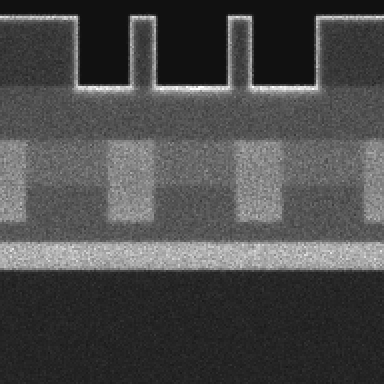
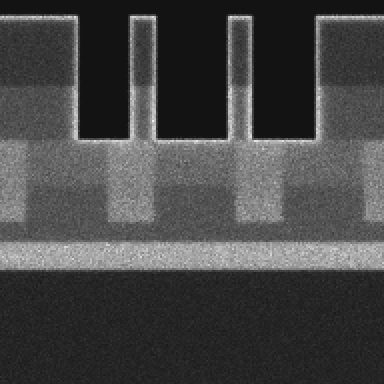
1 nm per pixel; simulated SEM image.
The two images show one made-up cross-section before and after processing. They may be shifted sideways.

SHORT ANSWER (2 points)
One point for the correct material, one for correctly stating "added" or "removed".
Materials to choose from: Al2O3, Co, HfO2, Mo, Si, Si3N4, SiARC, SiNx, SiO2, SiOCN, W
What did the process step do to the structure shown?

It removed SiO2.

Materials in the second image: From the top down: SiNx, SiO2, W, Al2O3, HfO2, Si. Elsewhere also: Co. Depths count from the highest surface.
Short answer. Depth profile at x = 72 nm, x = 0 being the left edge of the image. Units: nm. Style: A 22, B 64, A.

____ SiNx 70, SiO2 54, Co 46, Al2O3 56, HfO2 28, Si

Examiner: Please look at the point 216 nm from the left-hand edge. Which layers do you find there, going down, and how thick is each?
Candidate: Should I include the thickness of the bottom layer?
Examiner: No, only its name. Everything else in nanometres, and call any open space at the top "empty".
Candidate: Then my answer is empty 124, Co 46, Al2O3 56, HfO2 28, Si